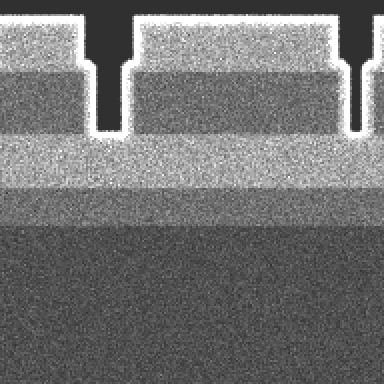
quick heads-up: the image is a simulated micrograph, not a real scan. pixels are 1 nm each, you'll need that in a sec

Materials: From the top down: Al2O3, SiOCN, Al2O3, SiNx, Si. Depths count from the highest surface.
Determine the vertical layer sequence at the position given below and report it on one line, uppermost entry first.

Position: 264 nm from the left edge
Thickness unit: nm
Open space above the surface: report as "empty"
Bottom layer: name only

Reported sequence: Al2O3 56, SiOCN 62, Al2O3 54, SiNx 38, Si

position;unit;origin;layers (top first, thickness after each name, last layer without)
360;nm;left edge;empty 116, Al2O3 56, SiNx 38, Si